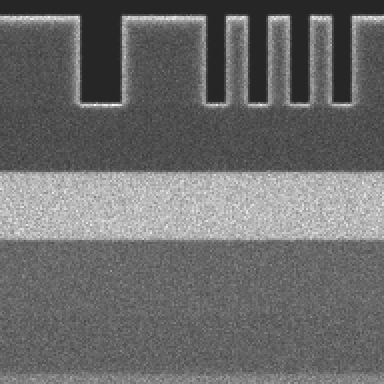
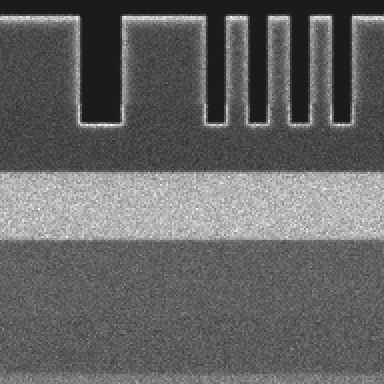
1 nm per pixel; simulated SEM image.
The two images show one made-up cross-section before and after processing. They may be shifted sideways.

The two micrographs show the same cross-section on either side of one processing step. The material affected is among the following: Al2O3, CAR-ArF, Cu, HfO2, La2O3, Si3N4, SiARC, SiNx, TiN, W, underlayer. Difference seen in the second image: TiN removed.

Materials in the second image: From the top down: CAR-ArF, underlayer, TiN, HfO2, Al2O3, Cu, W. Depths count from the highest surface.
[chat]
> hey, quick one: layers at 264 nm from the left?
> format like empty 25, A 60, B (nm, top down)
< empty 108, TiN 48, HfO2 68, Al2O3 76, Cu 58, W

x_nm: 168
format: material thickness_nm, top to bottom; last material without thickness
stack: CAR-ArF 66, underlayer 22, TiN 68, HfO2 68, Al2O3 76, Cu 58, W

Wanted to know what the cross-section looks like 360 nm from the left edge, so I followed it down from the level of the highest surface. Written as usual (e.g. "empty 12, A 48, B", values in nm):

CAR-ArF 66, underlayer 22, TiN 68, HfO2 68, Al2O3 76, Cu 58, W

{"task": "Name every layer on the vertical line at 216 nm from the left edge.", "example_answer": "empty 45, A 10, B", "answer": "empty 108, TiN 48, HfO2 68, Al2O3 76, Cu 58, W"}